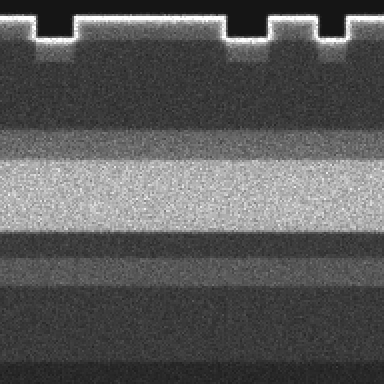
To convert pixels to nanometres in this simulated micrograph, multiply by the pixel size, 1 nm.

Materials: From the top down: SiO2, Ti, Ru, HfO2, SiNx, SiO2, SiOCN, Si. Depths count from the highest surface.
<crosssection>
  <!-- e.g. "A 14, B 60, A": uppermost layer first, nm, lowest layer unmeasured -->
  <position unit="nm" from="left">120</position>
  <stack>SiO2 24, Ti 90, Ru 30, HfO2 72, SiNx 26, SiO2 28, SiOCN 76, Si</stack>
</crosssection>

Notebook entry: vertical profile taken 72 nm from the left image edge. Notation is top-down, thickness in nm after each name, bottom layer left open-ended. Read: empty 22, SiO2 24, Ti 68, Ru 30, HfO2 72, SiNx 26, SiO2 28, SiOCN 76, Si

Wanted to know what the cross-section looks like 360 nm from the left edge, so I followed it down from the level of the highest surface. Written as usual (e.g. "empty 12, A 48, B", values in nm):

SiO2 24, Ti 90, Ru 30, HfO2 72, SiNx 26, SiO2 28, SiOCN 76, Si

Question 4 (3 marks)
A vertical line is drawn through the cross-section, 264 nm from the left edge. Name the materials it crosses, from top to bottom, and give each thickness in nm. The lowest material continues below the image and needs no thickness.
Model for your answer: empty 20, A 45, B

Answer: empty 22, SiO2 24, Ti 68, Ru 30, HfO2 72, SiNx 26, SiO2 28, SiOCN 76, Si